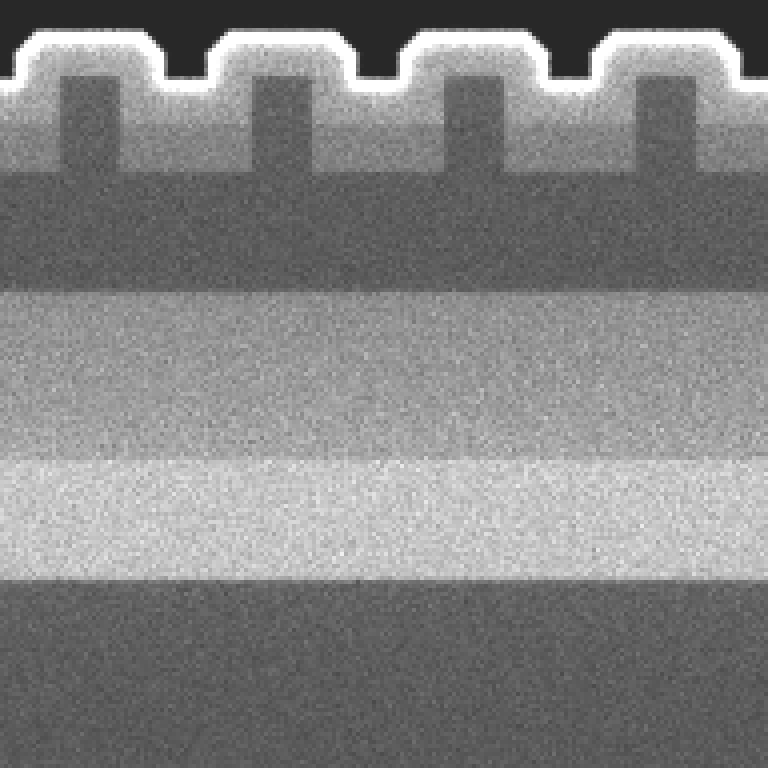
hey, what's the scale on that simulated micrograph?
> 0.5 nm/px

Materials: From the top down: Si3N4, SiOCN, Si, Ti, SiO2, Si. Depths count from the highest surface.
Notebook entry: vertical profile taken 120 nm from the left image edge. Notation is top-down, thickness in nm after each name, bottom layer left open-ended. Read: Si3N4 46, SiOCN 24, Si 60, Ti 84, SiO2 60, Si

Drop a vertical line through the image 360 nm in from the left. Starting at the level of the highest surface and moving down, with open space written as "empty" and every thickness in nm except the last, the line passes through empty 2, Si3N4 44, SiOCN 24, Si 60, Ti 84, SiO2 60, Si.